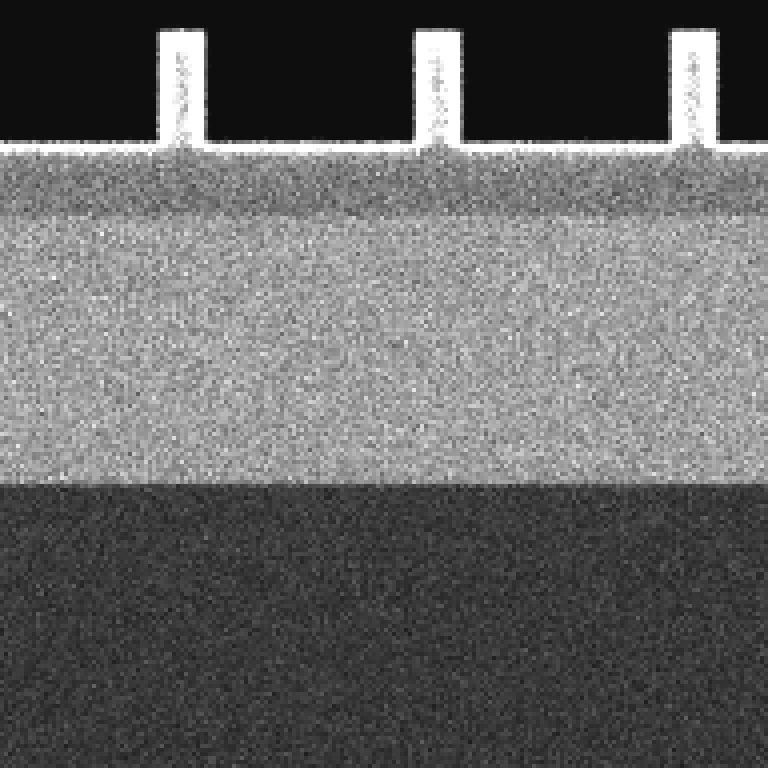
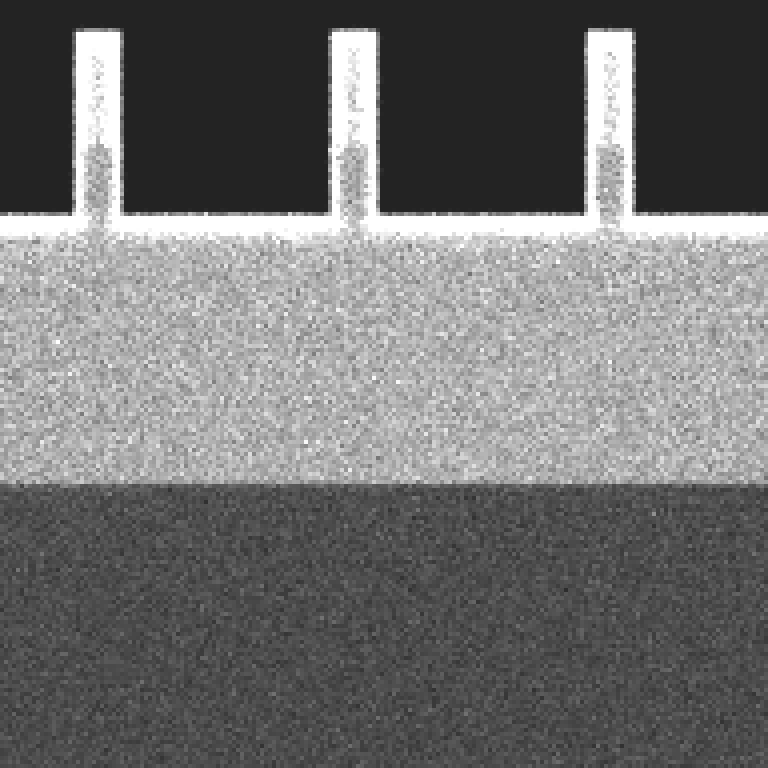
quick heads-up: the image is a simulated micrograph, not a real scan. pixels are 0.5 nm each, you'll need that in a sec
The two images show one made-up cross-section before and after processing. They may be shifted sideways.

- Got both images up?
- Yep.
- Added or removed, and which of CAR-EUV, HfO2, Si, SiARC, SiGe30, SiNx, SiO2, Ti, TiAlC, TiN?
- removed, TiN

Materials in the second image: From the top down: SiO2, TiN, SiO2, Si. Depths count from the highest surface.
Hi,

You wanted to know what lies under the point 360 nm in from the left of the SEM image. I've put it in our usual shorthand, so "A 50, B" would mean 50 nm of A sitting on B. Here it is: empty 92, SiO2 134, Si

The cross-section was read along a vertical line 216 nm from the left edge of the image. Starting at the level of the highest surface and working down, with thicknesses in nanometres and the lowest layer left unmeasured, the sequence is empty 92, SiO2 134, Si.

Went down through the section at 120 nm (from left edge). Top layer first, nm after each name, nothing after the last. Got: empty 92, SiO2 134, Si